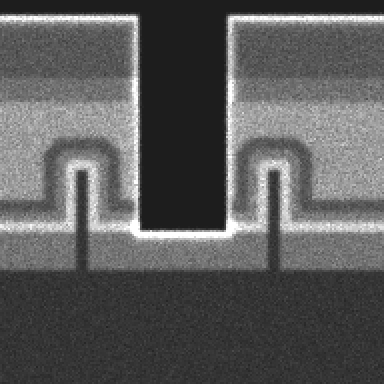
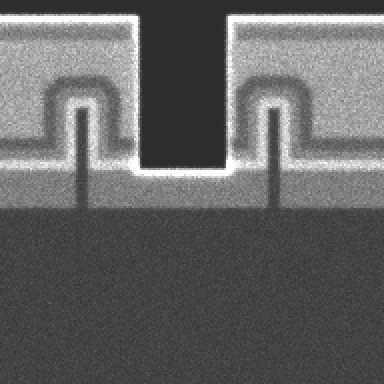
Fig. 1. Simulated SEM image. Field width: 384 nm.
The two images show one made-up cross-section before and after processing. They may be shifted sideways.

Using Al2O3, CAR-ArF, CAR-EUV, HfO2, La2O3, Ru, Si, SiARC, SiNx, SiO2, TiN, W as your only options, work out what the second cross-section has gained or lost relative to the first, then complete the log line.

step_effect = removed SiARC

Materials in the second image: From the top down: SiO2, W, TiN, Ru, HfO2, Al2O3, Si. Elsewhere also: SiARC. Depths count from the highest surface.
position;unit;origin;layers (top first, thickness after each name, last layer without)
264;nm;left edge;SiO2 24, W 36, TiN 12, Ru 10, HfO2 72, Al2O3 38, Si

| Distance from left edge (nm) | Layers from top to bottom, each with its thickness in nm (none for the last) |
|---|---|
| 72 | SiO2 24, W 36, TiN 12, Ru 10, HfO2 72, Al2O3 38, Si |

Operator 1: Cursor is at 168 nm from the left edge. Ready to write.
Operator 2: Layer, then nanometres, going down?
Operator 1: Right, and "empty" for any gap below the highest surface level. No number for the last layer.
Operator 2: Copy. empty 154, Al2O3 38, Si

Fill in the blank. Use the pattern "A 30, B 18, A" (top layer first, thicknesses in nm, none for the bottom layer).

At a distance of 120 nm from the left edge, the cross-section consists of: SiO2 24, W 98, TiN 12, Ru 10, HfO2 10, Al2O3 38, Si